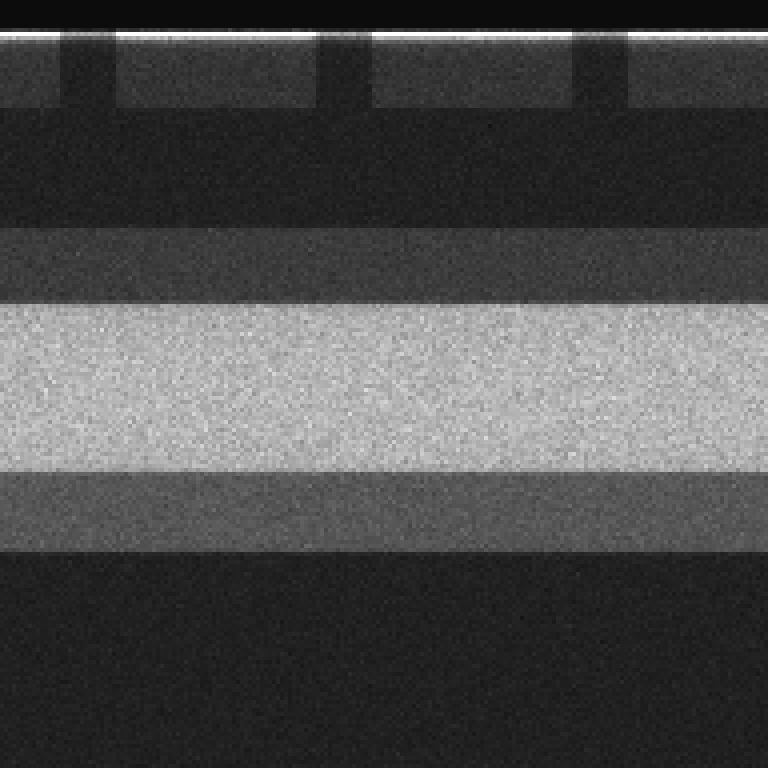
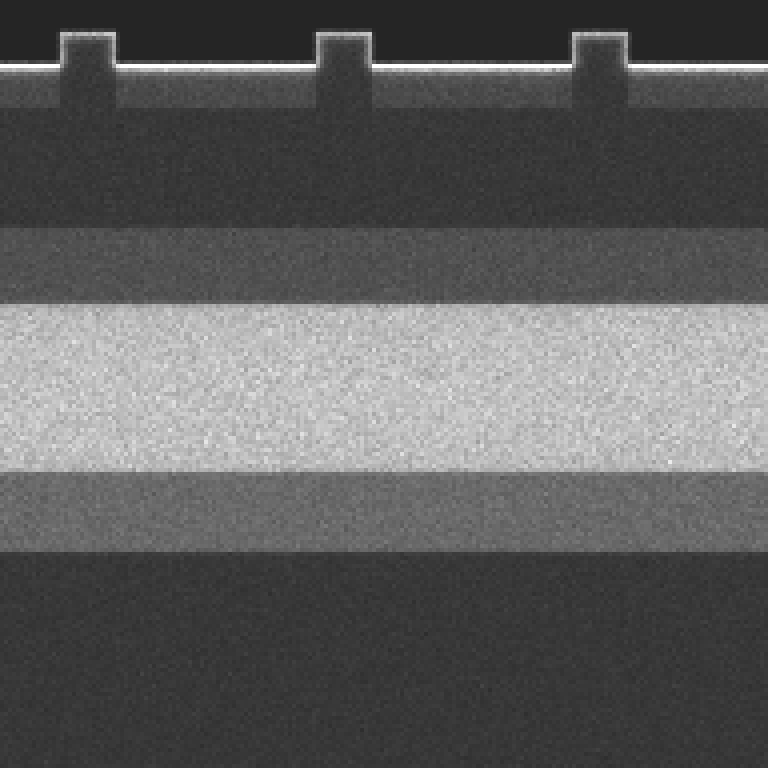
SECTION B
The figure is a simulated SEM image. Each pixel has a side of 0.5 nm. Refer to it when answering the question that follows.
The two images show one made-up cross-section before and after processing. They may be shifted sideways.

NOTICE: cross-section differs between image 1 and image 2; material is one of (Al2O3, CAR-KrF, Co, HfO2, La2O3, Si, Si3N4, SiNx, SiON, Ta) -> removed: SiNx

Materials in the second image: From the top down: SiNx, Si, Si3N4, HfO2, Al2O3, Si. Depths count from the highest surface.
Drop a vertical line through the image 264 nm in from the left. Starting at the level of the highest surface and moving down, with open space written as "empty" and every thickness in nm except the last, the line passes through empty 16, SiNx 22, Si 60, Si3N4 38, HfO2 84, Al2O3 40, Si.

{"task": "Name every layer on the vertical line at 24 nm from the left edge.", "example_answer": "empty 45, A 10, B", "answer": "empty 16, SiNx 22, Si 60, Si3N4 38, HfO2 84, Al2O3 40, Si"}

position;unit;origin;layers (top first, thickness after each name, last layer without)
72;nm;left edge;empty 16, SiNx 22, Si 60, Si3N4 38, HfO2 84, Al2O3 40, Si